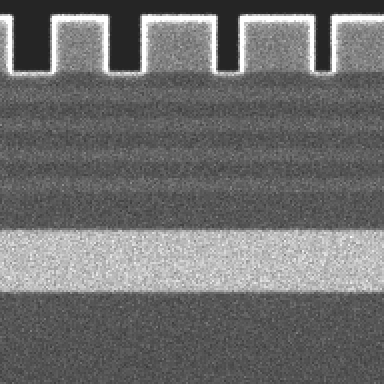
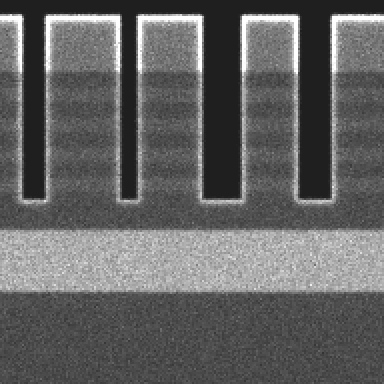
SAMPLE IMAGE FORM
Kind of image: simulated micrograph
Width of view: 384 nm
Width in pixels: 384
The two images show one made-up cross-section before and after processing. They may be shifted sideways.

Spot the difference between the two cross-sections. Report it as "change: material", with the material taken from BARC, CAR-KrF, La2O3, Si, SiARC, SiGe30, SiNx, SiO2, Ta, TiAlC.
removed: Si and SiGe30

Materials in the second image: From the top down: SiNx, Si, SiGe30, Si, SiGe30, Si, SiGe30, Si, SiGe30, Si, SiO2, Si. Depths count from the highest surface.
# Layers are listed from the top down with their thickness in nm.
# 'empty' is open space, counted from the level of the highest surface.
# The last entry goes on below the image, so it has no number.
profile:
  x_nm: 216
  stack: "empty 184, Si 30, SiO2 62, Si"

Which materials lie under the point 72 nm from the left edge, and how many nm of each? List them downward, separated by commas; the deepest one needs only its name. SiNx 56, Si 16, SiGe30 14, Si 16, SiGe30 14, Si 16, SiGe30 14, Si 16, SiGe30 14, Si 38, SiO2 62, Si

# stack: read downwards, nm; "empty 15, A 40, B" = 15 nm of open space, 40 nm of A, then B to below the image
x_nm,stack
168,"SiNx 56, Si 16, SiGe30 14, Si 16, SiGe30 14, Si 16, SiGe30 14, Si 16, SiGe30 14, Si 38, SiO2 62, Si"